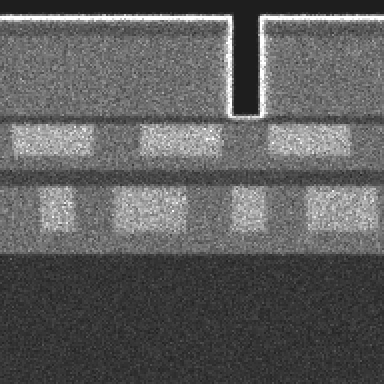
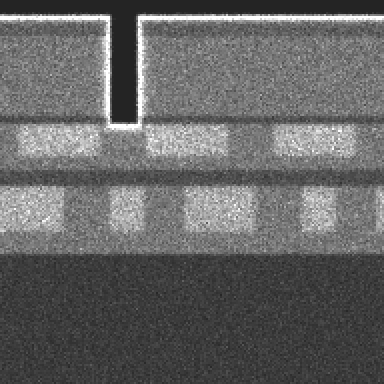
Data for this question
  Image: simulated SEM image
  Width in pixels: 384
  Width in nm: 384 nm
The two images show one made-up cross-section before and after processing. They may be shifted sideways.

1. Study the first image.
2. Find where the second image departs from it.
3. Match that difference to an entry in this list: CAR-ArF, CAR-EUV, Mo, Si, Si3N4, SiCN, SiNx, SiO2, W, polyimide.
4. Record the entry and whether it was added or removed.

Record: SiCN / removed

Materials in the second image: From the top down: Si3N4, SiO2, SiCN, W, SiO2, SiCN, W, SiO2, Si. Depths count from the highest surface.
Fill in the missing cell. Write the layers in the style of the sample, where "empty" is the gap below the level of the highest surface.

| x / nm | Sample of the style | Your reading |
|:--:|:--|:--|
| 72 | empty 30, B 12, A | Si3N4 20, SiO2 80, SiCN 8, W 32, SiO2 14, SiCN 16, SiO2 68, Si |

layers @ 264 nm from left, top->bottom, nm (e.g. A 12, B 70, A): Si3N4 20, SiO2 80, SiCN 8, SiO2 46, SiCN 16, SiO2 68, Si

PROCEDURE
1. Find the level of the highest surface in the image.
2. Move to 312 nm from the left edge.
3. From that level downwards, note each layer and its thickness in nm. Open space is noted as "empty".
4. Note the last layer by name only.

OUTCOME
Si3N4 20, SiO2 80, SiCN 8, W 32, SiO2 14, SiCN 16, W 46, SiO2 22, Si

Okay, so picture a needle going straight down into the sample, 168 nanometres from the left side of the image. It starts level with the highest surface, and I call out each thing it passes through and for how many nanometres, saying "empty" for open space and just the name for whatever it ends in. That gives Si3N4 20, SiO2 80, SiCN 8, W 32, SiO2 14, SiCN 16, SiO2 68, Si